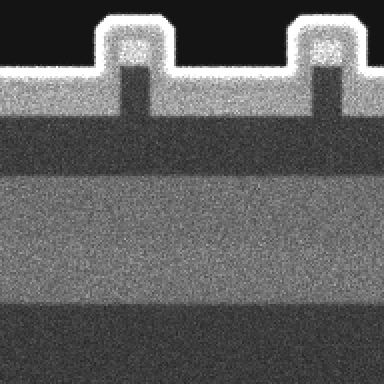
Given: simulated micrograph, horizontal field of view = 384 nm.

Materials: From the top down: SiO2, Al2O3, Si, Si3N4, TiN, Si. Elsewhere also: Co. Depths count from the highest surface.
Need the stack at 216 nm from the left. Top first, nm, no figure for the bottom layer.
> empty 52, SiO2 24, Al2O3 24, Si 60, Si3N4 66, TiN 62, Si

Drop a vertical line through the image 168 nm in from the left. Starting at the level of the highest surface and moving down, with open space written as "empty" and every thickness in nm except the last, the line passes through empty 8, SiO2 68, Al2O3 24, Si 60, Si3N4 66, TiN 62, Si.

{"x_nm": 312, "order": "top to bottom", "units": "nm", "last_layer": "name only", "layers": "SiO2 24, Co 26, Si 110, Si3N4 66, TiN 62, Si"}